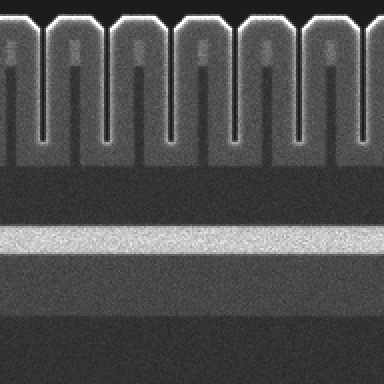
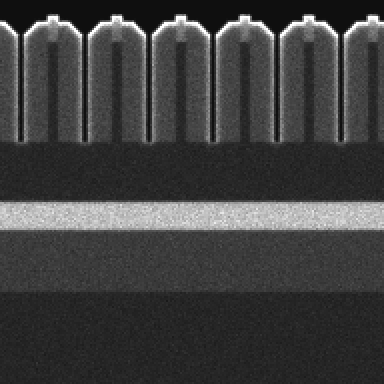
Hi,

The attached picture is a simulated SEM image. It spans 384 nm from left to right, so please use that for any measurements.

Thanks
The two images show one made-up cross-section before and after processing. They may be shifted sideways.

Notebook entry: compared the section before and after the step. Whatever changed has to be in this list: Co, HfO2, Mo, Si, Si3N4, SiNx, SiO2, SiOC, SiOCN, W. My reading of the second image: Si3N4 removed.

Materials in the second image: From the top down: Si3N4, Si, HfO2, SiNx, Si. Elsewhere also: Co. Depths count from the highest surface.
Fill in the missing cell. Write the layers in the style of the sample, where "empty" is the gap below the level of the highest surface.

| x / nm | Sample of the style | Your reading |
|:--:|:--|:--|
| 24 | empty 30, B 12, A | empty 18, Si3N4 108, Si 60, HfO2 28, SiNx 62, Si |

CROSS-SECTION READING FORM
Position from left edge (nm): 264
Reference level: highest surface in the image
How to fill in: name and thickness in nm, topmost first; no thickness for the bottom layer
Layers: empty 10, Si3N4 116, Si 60, HfO2 28, SiNx 62, Si